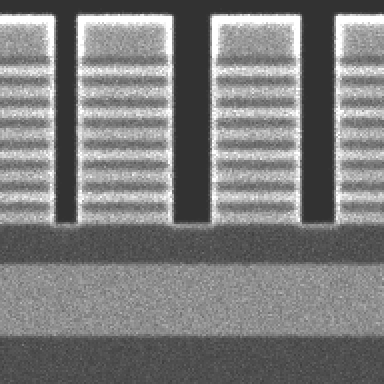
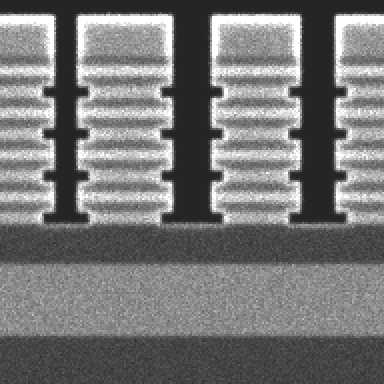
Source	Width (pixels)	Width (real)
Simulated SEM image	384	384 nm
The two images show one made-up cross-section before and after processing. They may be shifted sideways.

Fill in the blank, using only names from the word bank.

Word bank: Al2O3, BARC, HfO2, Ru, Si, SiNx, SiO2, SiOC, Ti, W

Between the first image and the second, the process removed Ru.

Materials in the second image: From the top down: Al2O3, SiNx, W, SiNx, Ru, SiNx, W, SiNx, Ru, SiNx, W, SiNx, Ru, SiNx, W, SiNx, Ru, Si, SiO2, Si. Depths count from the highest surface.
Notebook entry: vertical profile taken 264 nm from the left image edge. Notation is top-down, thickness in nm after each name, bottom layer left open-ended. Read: Al2O3 40, SiNx 10, W 10, SiNx 10, Ru 12, SiNx 10, W 10, SiNx 10, Ru 12, SiNx 10, W 10, SiNx 10, Ru 12, SiNx 10, W 10, SiNx 10, Ru 12, Si 40, SiO2 72, Si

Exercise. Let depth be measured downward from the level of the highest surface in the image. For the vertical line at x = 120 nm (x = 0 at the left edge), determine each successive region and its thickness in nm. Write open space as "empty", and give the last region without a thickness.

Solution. Al2O3 40, SiNx 10, W 10, SiNx 10, Ru 12, SiNx 10, W 10, SiNx 10, Ru 12, SiNx 10, W 10, SiNx 10, Ru 12, SiNx 10, W 10, SiNx 10, Ru 12, Si 40, SiO2 72, Si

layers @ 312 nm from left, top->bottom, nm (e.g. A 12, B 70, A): empty 208, Si 40, SiO2 72, Si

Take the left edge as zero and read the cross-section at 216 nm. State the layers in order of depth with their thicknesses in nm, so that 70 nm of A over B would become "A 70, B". Al2O3 40, SiNx 10, W 10, SiNx 10, empty 12, SiNx 10, W 10, SiNx 10, empty 12, SiNx 10, W 10, SiNx 10, empty 12, SiNx 10, W 10, SiNx 10, empty 12, Si 40, SiO2 72, Si